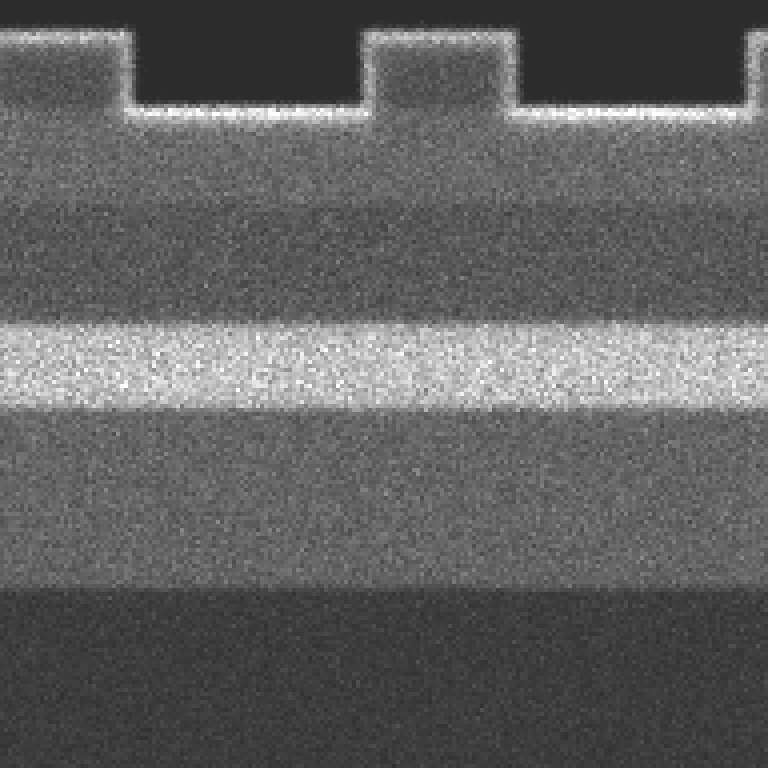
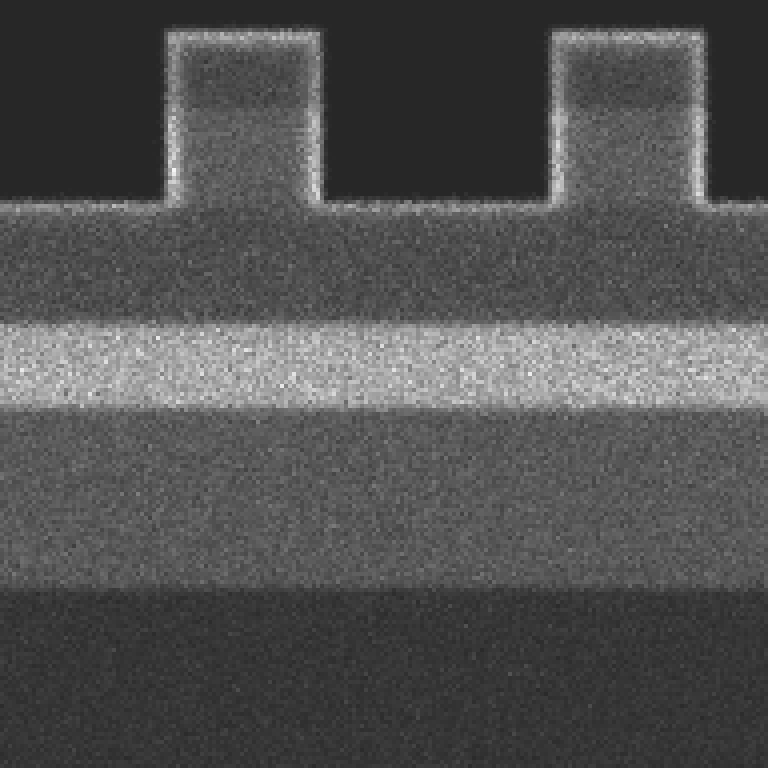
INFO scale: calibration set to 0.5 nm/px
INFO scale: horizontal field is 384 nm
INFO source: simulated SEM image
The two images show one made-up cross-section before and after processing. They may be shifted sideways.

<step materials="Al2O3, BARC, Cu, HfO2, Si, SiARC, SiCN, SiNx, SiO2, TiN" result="removed Al2O3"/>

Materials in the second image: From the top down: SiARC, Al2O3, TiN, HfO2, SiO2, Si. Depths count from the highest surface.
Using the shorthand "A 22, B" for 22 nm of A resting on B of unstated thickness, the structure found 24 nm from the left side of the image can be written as empty 86, TiN 60, HfO2 42, SiO2 90, Si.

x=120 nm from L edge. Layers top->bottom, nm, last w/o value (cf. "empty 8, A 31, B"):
SiARC 38, Al2O3 48, TiN 60, HfO2 42, SiO2 90, Si